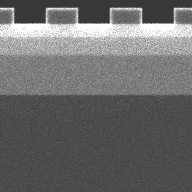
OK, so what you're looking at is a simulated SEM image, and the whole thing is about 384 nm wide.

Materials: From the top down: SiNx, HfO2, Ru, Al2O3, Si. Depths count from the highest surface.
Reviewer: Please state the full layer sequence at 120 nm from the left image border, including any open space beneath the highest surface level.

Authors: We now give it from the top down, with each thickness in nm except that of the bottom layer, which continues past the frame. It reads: SiNx 32, HfO2 26, Ru 36, Al2O3 80, Si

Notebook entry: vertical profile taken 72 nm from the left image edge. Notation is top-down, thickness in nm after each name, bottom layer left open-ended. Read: empty 32, HfO2 26, Ru 36, Al2O3 80, Si